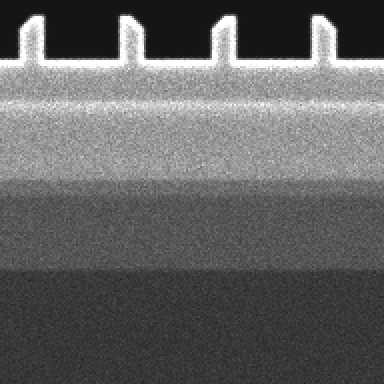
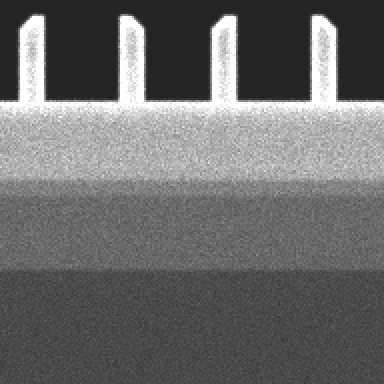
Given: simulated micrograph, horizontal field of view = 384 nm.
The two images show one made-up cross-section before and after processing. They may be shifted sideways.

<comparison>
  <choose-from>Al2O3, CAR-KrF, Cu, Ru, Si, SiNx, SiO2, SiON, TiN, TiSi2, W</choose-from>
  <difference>Al2O3 removed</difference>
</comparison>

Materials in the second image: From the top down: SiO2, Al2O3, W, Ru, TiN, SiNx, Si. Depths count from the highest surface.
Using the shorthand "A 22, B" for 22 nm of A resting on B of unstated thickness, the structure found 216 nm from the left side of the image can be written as empty 8, SiO2 36, Al2O3 42, W 68, Ru 10, TiN 16, SiNx 74, Si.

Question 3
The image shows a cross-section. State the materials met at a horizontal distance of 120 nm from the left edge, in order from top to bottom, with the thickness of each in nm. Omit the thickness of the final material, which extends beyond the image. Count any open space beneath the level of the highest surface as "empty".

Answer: SiO2 44, Al2O3 42, W 68, Ru 10, TiN 16, SiNx 74, Si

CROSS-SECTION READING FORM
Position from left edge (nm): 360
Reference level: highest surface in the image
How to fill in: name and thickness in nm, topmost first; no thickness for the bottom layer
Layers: empty 86, W 68, Ru 10, TiN 16, SiNx 74, Si